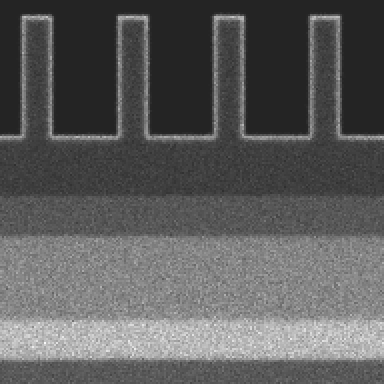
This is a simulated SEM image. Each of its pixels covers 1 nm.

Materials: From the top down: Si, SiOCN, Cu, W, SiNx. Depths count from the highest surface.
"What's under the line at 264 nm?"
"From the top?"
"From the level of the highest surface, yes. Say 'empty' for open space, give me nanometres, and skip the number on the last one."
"empty 120, Si 60, SiOCN 40, Cu 84, W 40, SiNx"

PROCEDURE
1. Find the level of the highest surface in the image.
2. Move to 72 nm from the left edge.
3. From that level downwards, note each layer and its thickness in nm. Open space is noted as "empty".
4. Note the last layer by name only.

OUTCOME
empty 120, Si 60, SiOCN 40, Cu 84, W 40, SiNx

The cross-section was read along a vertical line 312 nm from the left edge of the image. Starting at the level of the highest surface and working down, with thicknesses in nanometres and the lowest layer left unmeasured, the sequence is Si 180, SiOCN 40, Cu 84, W 40, SiNx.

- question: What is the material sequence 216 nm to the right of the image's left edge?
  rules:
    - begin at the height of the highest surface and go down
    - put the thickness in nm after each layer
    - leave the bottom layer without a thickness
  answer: Si 180, SiOCN 40, Cu 84, W 40, SiNx